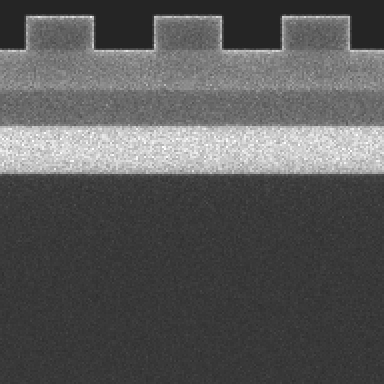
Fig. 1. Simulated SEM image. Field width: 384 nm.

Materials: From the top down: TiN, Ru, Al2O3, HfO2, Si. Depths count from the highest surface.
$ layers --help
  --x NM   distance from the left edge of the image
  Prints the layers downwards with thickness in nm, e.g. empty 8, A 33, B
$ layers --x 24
empty 34, Ru 40, Al2O3 36, HfO2 48, Si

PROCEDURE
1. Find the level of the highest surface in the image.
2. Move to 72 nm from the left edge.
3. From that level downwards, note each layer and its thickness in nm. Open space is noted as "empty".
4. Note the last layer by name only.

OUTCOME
TiN 34, Ru 40, Al2O3 36, HfO2 48, Si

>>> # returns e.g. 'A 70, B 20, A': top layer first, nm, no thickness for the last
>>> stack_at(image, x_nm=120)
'empty 34, Ru 40, Al2O3 36, HfO2 48, Si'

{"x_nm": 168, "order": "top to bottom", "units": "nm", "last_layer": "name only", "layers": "TiN 34, Ru 40, Al2O3 36, HfO2 48, Si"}